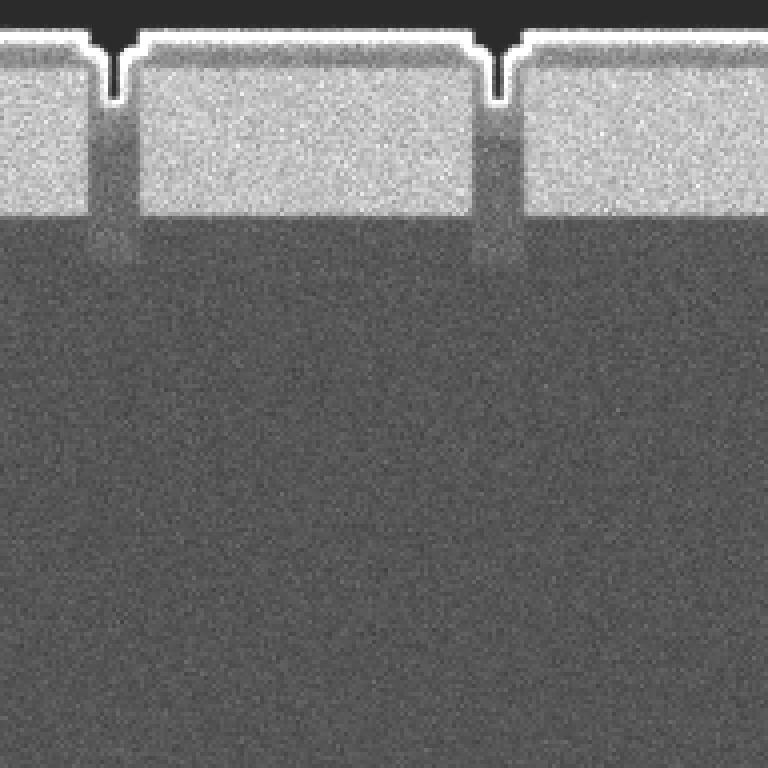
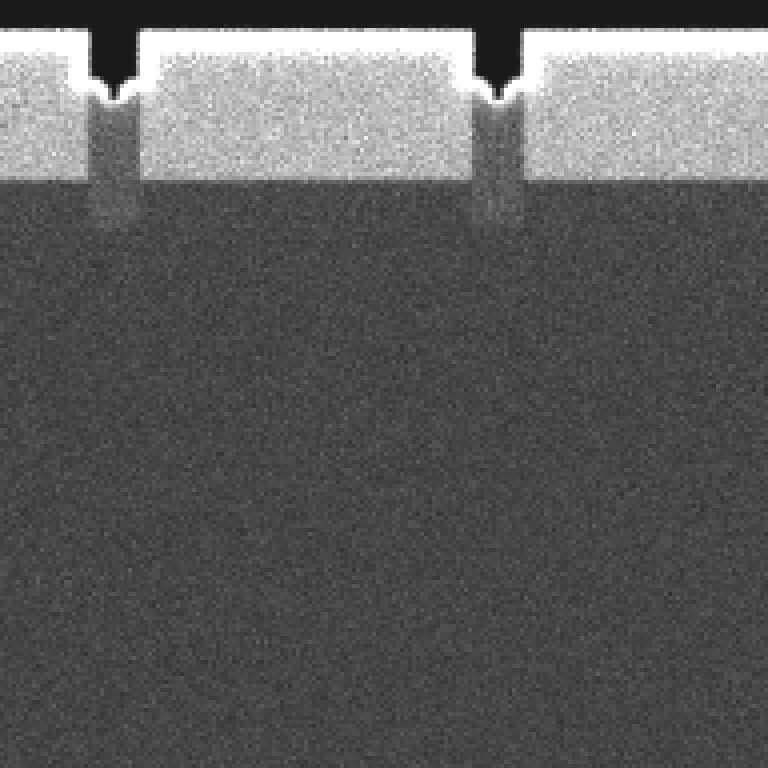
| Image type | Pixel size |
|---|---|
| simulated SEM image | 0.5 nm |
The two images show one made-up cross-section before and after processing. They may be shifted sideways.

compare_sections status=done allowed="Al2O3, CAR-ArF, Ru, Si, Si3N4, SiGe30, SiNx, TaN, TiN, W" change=removed material="SiNx"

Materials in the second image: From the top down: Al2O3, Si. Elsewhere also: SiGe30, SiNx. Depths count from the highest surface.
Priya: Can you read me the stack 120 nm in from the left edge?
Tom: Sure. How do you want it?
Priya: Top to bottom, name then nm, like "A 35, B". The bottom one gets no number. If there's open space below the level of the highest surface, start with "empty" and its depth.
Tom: Al2O3 74, Si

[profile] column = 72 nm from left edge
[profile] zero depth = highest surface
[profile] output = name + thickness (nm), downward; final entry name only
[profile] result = Al2O3 74, Si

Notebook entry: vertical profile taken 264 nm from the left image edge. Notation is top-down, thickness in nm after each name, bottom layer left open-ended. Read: Al2O3 74, Si